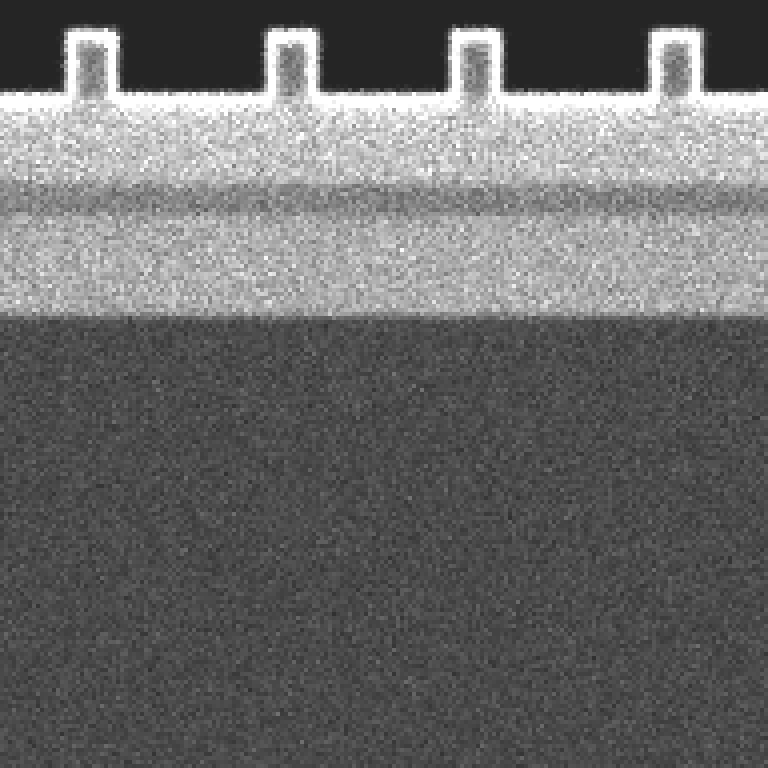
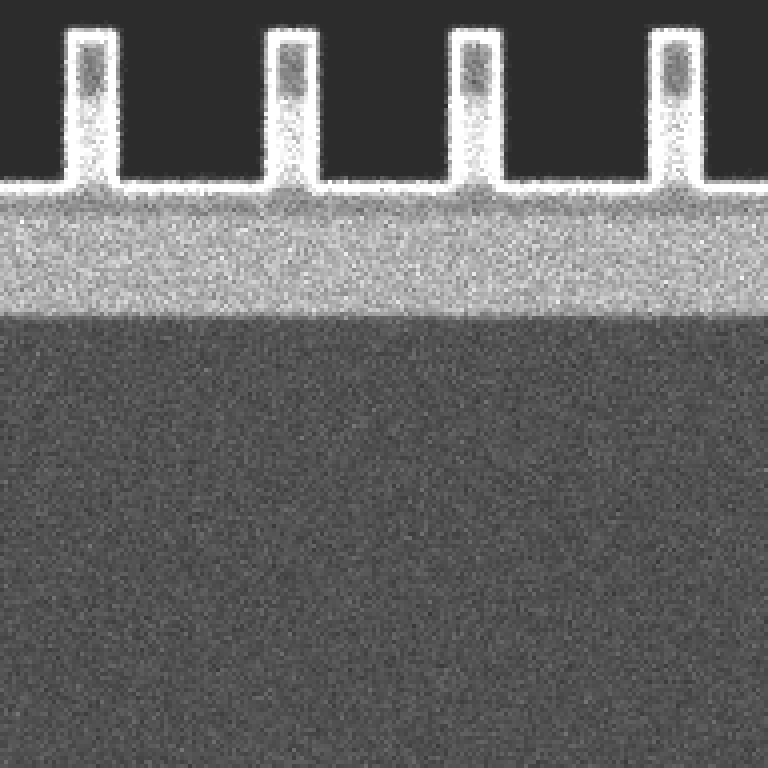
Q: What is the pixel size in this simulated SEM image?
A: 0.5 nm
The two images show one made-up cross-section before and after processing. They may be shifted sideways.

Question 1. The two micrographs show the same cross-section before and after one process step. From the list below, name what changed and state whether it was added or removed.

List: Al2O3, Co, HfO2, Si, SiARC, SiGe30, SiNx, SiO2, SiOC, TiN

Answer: Co, removed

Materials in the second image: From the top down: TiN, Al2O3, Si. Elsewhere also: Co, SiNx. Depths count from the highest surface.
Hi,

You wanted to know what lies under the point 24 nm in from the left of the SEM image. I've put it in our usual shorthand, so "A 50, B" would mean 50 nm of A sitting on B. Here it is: empty 76, TiN 16, Al2O3 50, Si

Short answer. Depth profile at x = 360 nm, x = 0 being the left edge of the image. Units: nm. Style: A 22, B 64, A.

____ empty 76, TiN 16, Al2O3 50, Si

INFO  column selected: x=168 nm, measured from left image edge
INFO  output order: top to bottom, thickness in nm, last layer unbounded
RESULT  empty 76, TiN 16, Al2O3 50, Si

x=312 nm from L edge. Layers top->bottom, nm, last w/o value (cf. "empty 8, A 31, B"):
empty 76, TiN 16, Al2O3 50, Si